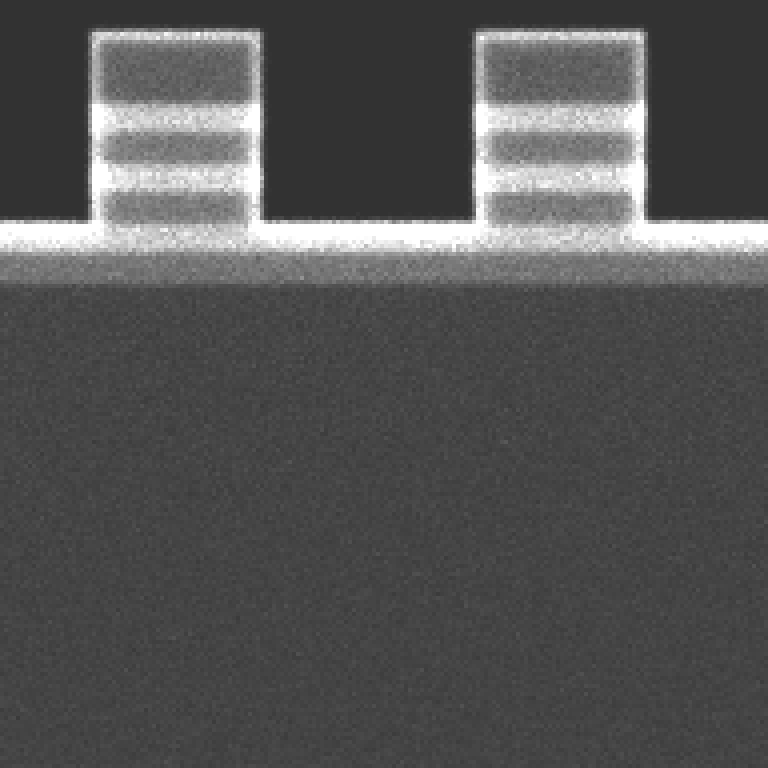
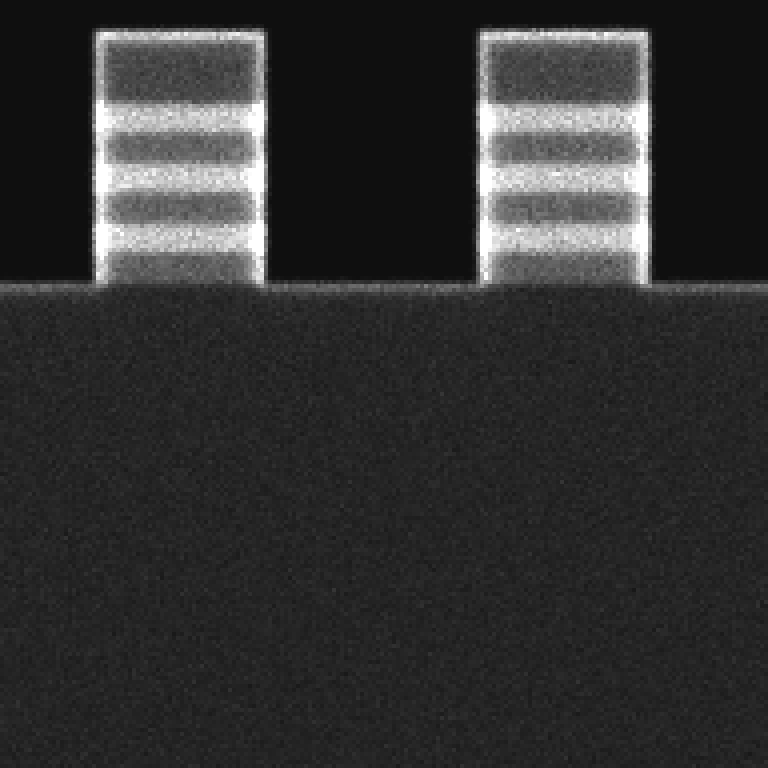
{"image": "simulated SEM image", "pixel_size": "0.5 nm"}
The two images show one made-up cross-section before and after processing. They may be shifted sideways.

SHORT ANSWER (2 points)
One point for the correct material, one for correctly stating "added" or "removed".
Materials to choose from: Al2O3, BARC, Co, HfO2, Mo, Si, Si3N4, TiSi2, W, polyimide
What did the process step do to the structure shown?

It removed Al2O3 and HfO2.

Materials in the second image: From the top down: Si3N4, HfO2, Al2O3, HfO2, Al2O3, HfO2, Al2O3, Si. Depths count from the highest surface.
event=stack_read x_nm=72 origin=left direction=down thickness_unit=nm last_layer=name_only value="Si3N4 36, HfO2 14, Al2O3 16, HfO2 14, Al2O3 16, HfO2 14, Al2O3 16, Si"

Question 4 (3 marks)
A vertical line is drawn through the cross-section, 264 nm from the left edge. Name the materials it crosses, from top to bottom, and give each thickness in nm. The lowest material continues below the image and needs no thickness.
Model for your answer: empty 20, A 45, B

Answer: Si3N4 36, HfO2 14, Al2O3 16, HfO2 14, Al2O3 16, HfO2 14, Al2O3 16, Si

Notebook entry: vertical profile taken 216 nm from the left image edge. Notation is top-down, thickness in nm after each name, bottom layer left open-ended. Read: empty 126, Si